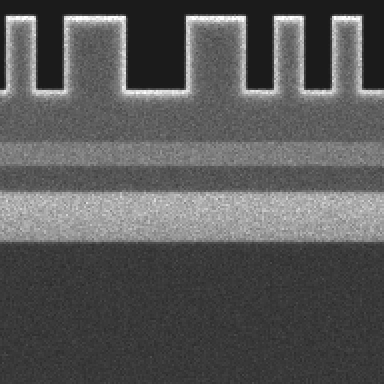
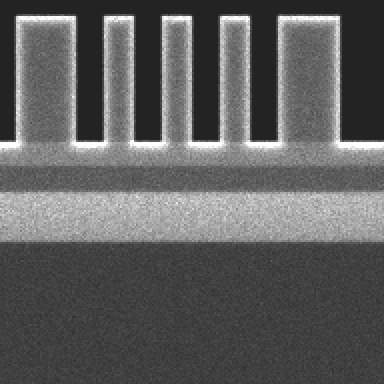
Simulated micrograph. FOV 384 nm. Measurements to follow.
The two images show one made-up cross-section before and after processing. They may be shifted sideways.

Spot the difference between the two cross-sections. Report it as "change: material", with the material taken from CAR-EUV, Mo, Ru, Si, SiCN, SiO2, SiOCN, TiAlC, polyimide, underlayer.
removed: underlayer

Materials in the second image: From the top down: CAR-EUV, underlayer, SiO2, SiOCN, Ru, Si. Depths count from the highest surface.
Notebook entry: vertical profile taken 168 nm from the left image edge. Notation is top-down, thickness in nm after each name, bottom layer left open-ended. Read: CAR-EUV 74, underlayer 52, SiO2 24, SiOCN 26, Ru 50, Si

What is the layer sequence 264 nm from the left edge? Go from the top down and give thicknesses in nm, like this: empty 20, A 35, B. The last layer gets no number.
empty 126, SiO2 24, SiOCN 26, Ru 50, Si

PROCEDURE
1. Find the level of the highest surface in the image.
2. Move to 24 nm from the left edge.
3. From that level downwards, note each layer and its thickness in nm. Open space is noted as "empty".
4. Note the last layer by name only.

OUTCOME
CAR-EUV 74, underlayer 52, SiO2 24, SiOCN 26, Ru 50, Si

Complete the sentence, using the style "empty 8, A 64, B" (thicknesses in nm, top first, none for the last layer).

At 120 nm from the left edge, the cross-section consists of CAR-EUV 74, underlayer 52, SiO2 24, SiOCN 26, Ru 50, Si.